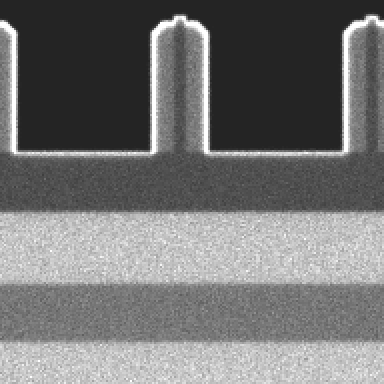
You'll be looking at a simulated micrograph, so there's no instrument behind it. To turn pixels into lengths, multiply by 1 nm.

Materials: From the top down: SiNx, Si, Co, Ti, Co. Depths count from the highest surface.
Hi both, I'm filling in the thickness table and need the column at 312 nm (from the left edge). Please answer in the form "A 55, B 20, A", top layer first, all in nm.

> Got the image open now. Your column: empty 136, Si 60, Co 72, Ti 58, Co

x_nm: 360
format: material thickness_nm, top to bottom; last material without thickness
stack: empty 6, SiNx 130, Si 60, Co 72, Ti 58, Co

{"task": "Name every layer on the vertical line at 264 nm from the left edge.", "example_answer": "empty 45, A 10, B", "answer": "empty 136, Si 60, Co 72, Ti 58, Co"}